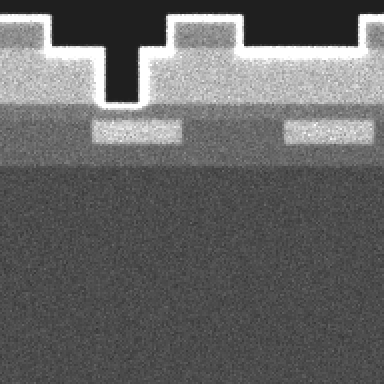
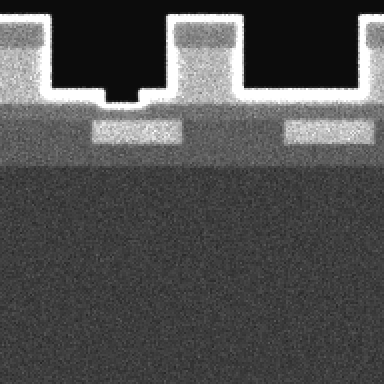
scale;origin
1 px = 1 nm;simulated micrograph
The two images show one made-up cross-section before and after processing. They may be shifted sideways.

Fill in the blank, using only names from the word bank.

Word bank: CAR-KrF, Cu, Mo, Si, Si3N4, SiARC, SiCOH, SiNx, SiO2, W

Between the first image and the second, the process removed SiO2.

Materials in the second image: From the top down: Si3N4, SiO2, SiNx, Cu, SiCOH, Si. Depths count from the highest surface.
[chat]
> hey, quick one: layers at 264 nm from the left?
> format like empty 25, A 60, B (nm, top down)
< empty 74, SiO2 14, SiNx 16, SiCOH 46, Si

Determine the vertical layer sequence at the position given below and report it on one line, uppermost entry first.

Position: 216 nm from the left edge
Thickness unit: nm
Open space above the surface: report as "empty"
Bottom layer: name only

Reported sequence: Si3N4 32, SiO2 56, SiNx 16, SiCOH 46, Si